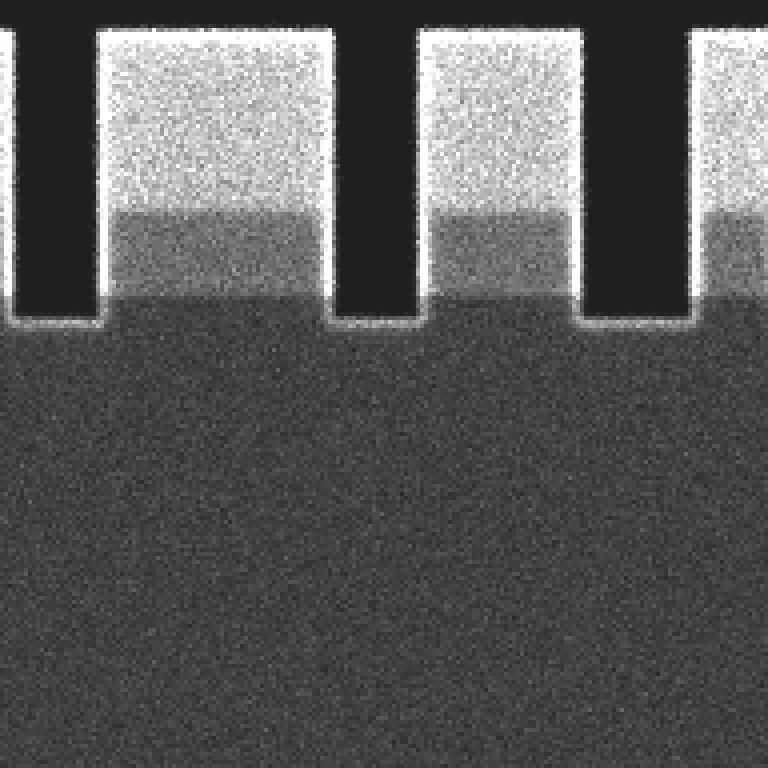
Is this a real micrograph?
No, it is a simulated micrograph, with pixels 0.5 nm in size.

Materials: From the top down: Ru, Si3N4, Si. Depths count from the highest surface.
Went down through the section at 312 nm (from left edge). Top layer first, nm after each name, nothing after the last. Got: empty 144, Si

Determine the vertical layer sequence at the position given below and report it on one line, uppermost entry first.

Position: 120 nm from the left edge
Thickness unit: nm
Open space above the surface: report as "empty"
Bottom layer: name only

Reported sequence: Ru 90, Si3N4 42, Si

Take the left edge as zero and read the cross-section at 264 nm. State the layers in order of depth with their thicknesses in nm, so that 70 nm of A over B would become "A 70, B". Ru 90, Si3N4 42, Si